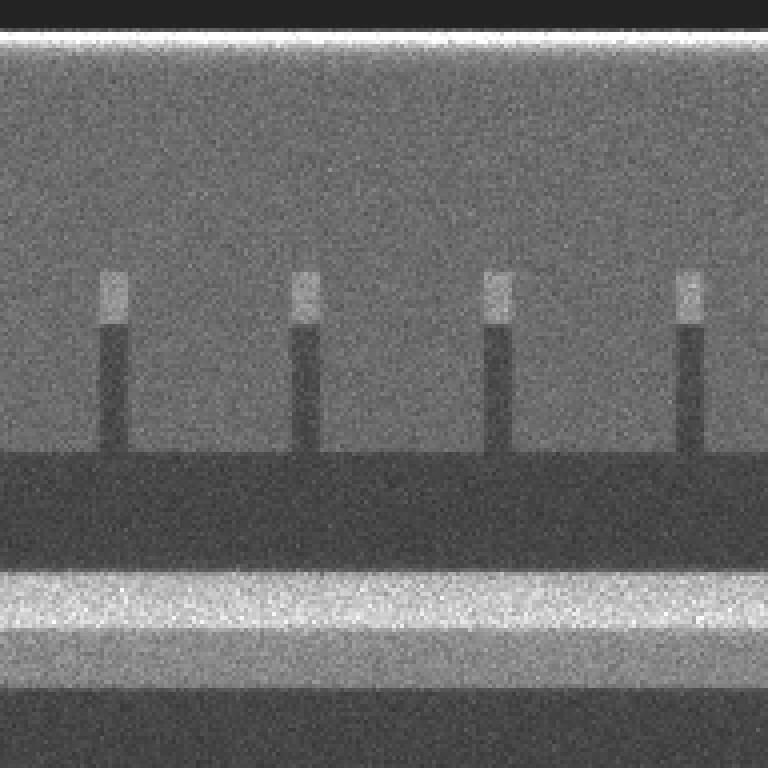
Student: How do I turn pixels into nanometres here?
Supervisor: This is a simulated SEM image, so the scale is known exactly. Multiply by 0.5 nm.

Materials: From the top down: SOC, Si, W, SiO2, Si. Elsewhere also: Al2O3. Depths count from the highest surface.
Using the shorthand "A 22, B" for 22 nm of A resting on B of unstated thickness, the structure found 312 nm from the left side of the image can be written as SOC 210, Si 60, W 28, SiO2 30, Si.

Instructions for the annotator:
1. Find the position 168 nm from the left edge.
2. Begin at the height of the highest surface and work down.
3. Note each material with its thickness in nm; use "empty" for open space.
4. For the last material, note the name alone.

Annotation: SOC 210, Si 60, W 28, SiO2 30, Si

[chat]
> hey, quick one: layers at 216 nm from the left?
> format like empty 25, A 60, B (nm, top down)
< SOC 210, Si 60, W 28, SiO2 30, Si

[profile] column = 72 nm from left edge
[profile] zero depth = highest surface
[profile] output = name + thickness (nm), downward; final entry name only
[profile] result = SOC 210, Si 60, W 28, SiO2 30, Si